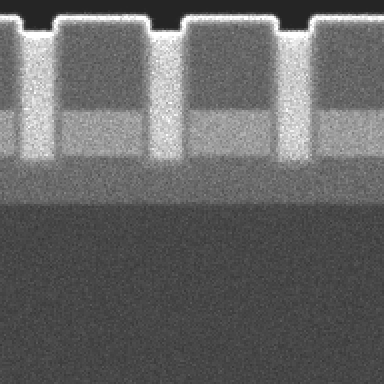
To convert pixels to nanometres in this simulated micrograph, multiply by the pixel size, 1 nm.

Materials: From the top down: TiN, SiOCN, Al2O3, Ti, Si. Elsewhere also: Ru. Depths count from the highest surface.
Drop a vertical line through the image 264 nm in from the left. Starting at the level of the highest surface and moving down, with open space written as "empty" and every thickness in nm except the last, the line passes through TiN 8, SiOCN 86, Al2O3 46, Ti 48, Si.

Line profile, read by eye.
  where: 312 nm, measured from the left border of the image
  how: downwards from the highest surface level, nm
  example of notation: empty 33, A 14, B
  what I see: empty 2, TiN 150, Ti 36, Si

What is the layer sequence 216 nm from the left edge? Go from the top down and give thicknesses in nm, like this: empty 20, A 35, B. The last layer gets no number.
TiN 8, SiOCN 86, Al2O3 46, Ti 48, Si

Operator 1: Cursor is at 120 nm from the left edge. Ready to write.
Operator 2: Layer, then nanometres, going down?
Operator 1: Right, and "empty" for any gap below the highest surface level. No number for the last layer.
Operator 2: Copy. TiN 8, SiOCN 86, Al2O3 46, Ti 48, Si